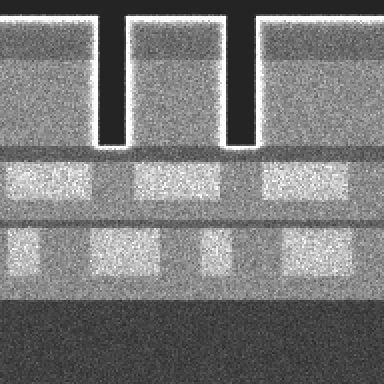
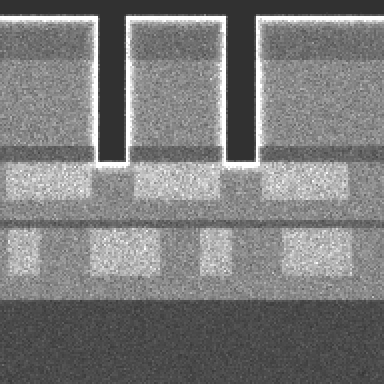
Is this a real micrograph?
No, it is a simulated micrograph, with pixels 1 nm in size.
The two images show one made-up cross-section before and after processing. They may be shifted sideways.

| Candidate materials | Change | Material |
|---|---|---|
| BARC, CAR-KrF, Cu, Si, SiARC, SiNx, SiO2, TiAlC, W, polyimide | removed | SiNx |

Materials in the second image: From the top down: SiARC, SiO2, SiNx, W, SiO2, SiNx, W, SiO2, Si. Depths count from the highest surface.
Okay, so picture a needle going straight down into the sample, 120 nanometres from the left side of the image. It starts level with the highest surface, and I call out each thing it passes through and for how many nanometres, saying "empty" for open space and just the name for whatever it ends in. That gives empty 146, SiO2 58, SiNx 8, W 48, SiO2 24, Si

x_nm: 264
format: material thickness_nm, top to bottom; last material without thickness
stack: SiARC 44, SiO2 86, SiNx 16, W 38, SiO2 20, SiNx 8, SiO2 72, Si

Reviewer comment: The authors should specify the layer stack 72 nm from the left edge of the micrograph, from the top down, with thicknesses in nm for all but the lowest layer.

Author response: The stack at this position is SiARC 44, SiO2 86, SiNx 16, W 38, SiO2 20, SiNx 8, SiO2 72, Si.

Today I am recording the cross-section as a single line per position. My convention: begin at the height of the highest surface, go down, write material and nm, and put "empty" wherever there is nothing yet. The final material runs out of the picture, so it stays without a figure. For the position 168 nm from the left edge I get SiARC 44, SiO2 86, SiNx 16, W 38, SiO2 20, SiNx 8, SiO2 72, Si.